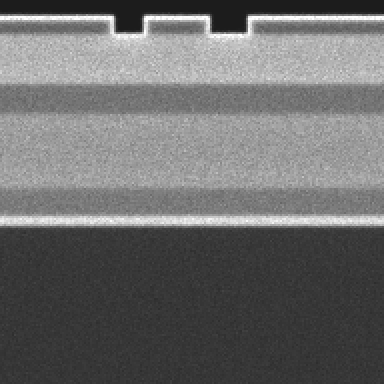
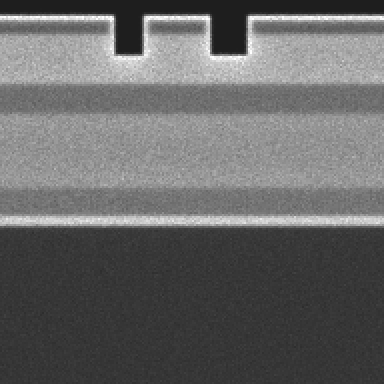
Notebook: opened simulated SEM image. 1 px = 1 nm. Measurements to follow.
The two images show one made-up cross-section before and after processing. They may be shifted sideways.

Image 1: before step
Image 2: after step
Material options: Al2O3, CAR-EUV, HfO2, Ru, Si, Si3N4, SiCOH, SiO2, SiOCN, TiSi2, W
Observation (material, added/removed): W, removed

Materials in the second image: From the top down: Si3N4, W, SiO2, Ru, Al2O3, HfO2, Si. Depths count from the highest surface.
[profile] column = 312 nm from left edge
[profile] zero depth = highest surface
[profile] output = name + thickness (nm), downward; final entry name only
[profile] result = Si3N4 18, W 50, SiO2 30, Ru 74, Al2O3 28, HfO2 10, Si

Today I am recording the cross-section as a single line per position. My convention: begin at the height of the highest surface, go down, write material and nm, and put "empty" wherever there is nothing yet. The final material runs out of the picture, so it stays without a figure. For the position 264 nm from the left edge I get Si3N4 18, W 50, SiO2 30, Ru 74, Al2O3 28, HfO2 10, Si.